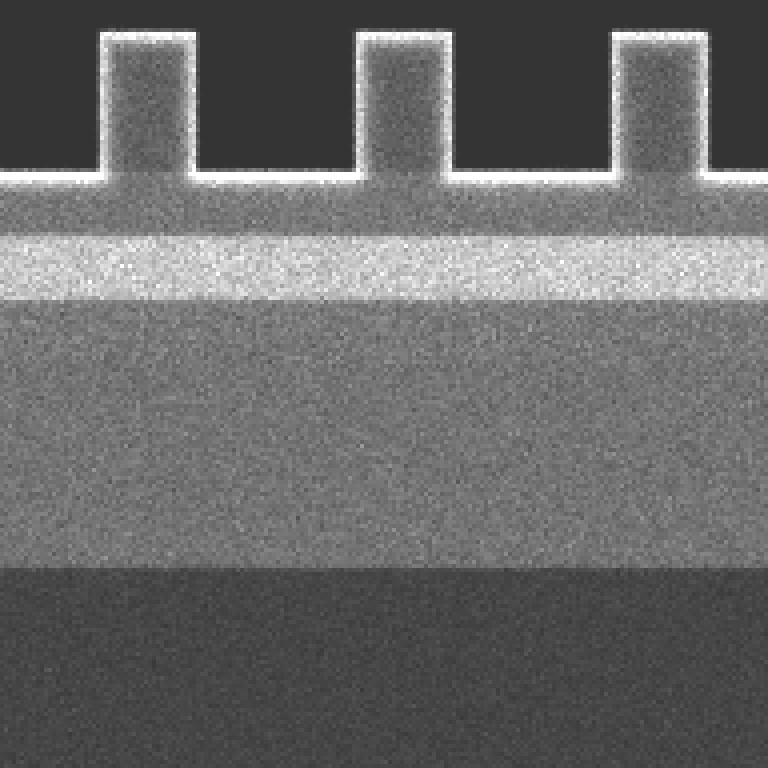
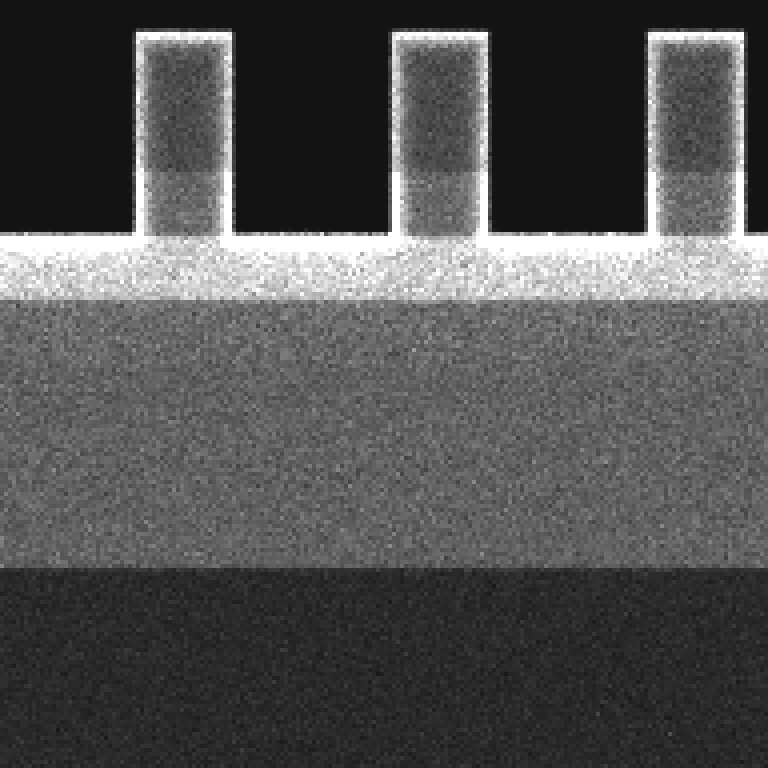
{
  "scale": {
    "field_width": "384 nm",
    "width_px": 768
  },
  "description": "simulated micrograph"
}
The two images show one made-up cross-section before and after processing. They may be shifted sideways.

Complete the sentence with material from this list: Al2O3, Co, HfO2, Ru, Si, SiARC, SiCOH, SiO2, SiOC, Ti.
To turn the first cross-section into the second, Al2O3 must be removed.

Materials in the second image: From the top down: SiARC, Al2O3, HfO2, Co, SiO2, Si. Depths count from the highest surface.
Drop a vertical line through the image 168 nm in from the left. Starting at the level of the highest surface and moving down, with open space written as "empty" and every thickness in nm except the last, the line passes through empty 102, HfO2 32, Co 32, SiO2 102, Si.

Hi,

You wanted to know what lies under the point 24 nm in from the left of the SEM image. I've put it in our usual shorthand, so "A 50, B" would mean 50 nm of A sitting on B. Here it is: empty 102, HfO2 32, Co 32, SiO2 102, Si